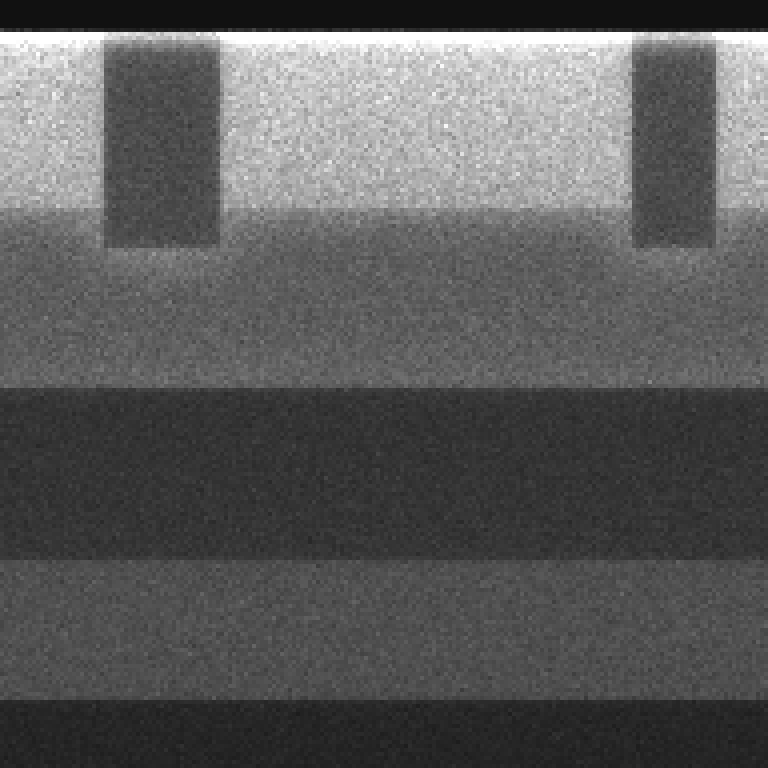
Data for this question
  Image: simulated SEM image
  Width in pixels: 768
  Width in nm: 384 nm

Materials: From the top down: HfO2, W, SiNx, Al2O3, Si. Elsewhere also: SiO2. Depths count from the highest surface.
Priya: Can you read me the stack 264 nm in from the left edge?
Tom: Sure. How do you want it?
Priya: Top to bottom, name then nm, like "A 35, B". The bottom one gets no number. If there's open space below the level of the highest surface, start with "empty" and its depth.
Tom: HfO2 88, W 90, SiNx 86, Al2O3 70, Si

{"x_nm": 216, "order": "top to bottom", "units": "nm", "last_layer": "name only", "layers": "HfO2 88, W 90, SiNx 86, Al2O3 70, Si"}